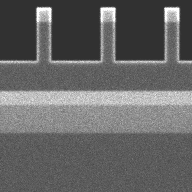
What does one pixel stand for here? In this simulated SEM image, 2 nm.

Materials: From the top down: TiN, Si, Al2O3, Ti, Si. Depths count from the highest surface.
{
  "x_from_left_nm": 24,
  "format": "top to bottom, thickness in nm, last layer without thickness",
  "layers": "empty 106, Si 60, Al2O3 28, Ti 56, Si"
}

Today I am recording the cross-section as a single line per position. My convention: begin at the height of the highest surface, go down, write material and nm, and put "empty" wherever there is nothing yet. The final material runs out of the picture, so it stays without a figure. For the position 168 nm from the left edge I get empty 106, Si 60, Al2O3 28, Ti 56, Si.